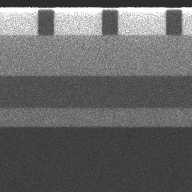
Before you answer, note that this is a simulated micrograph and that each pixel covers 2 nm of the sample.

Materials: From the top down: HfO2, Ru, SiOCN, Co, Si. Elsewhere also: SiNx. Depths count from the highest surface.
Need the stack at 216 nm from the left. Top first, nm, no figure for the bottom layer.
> SiNx 54, Ru 82, SiOCN 64, Co 38, Si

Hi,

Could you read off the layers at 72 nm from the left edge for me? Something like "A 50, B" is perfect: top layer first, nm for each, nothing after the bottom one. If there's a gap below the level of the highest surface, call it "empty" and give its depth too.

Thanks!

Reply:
HfO2 54, Ru 82, SiOCN 64, Co 38, Si